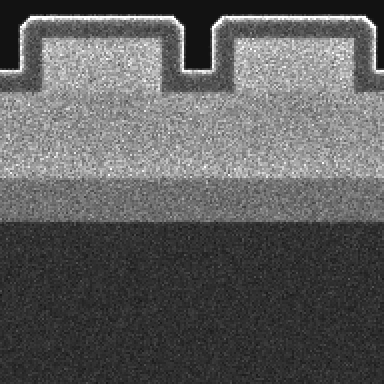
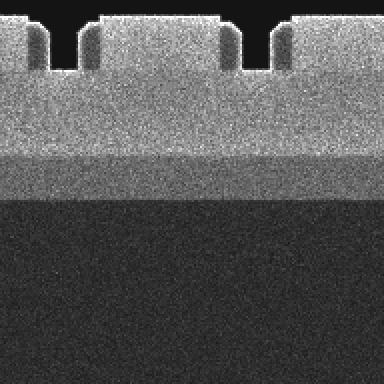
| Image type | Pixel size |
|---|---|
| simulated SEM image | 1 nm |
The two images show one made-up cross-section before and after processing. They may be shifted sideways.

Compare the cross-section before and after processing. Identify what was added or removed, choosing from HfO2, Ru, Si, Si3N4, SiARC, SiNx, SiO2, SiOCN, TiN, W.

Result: SiNx removed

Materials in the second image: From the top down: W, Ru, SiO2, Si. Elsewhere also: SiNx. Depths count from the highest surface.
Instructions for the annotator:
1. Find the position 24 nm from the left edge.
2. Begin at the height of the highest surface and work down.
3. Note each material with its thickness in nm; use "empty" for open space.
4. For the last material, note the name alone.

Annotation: W 54, Ru 86, SiO2 44, Si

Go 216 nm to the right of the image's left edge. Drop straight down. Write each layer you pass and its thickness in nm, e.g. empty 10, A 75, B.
W 54, Ru 86, SiO2 44, Si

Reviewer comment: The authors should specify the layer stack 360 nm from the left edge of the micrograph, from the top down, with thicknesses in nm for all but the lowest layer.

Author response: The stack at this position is W 54, Ru 86, SiO2 44, Si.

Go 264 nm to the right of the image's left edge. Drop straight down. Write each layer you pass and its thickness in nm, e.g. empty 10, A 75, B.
empty 54, Ru 86, SiO2 44, Si